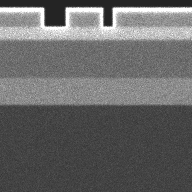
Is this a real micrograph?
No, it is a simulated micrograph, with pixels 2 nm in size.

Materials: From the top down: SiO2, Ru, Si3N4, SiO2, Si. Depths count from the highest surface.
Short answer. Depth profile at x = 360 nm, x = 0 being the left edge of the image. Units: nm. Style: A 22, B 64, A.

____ SiO2 38, Ru 26, Si3N4 76, SiO2 54, Si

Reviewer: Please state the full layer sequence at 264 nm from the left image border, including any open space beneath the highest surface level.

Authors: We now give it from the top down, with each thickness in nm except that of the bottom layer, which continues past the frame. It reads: SiO2 38, Ru 26, Si3N4 76, SiO2 54, Si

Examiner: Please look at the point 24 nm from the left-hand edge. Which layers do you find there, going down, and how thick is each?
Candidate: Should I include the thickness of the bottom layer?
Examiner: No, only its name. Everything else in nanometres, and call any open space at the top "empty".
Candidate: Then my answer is SiO2 38, Ru 26, Si3N4 76, SiO2 54, Si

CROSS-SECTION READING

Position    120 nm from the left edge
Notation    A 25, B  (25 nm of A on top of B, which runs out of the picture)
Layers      empty 38, Ru 26, Si3N4 76, SiO2 54, Si